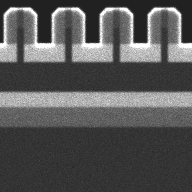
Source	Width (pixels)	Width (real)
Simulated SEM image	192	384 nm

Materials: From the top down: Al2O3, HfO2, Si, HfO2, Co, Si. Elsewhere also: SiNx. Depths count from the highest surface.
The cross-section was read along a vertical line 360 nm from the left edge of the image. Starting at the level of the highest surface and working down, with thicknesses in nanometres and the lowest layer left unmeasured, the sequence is empty 12, Al2O3 60, HfO2 36, Si 60, HfO2 30, Co 40, Si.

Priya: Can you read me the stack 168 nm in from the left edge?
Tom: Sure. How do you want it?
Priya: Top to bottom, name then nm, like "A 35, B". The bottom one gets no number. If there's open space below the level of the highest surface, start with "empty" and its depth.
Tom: empty 12, Al2O3 60, HfO2 36, Si 60, HfO2 30, Co 40, Si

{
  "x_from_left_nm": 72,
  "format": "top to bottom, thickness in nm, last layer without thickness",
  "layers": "empty 12, Al2O3 60, HfO2 36, Si 60, HfO2 30, Co 40, Si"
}